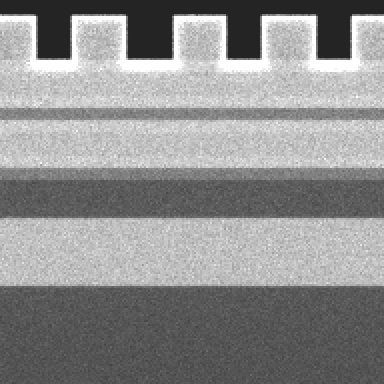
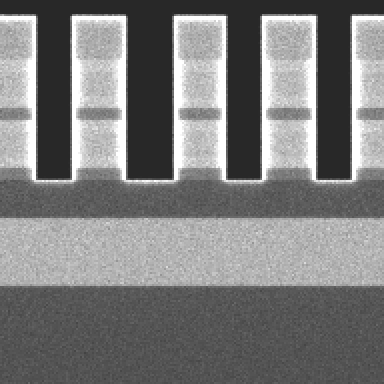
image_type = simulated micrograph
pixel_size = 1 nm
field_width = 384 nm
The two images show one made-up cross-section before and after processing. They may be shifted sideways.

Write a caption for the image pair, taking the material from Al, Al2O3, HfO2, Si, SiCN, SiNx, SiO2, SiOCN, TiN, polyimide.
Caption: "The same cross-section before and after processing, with Al2O3 and SiO2 and SiOCN removed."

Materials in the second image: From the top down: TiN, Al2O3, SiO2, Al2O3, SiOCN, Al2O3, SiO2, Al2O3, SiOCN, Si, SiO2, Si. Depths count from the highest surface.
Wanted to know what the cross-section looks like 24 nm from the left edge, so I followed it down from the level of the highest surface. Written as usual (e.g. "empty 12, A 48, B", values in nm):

TiN 44, Al2O3 12, SiO2 24, Al2O3 12, SiOCN 12, Al2O3 12, SiO2 24, Al2O3 12, SiOCN 12, Si 38, SiO2 68, Si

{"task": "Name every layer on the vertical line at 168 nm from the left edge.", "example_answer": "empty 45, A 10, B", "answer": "empty 164, Si 38, SiO2 68, Si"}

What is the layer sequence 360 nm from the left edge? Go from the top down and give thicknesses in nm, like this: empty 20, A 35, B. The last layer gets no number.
TiN 44, Al2O3 12, SiO2 24, Al2O3 12, SiOCN 12, Al2O3 12, SiO2 24, Al2O3 12, SiOCN 12, Si 38, SiO2 68, Si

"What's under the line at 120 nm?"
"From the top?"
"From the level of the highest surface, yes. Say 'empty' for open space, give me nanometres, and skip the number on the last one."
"TiN 44, Al2O3 12, SiO2 24, Al2O3 12, SiOCN 12, Al2O3 12, SiO2 24, Al2O3 12, SiOCN 12, Si 38, SiO2 68, Si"